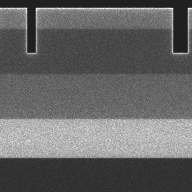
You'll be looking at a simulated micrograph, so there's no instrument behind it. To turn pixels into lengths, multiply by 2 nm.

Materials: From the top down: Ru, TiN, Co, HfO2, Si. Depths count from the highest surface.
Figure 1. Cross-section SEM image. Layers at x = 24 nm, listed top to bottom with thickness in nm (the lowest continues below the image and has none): Ru 42, TiN 90, Co 90, HfO2 78, Si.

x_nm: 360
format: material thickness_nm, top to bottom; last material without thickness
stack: empty 90, TiN 42, Co 90, HfO2 78, Si